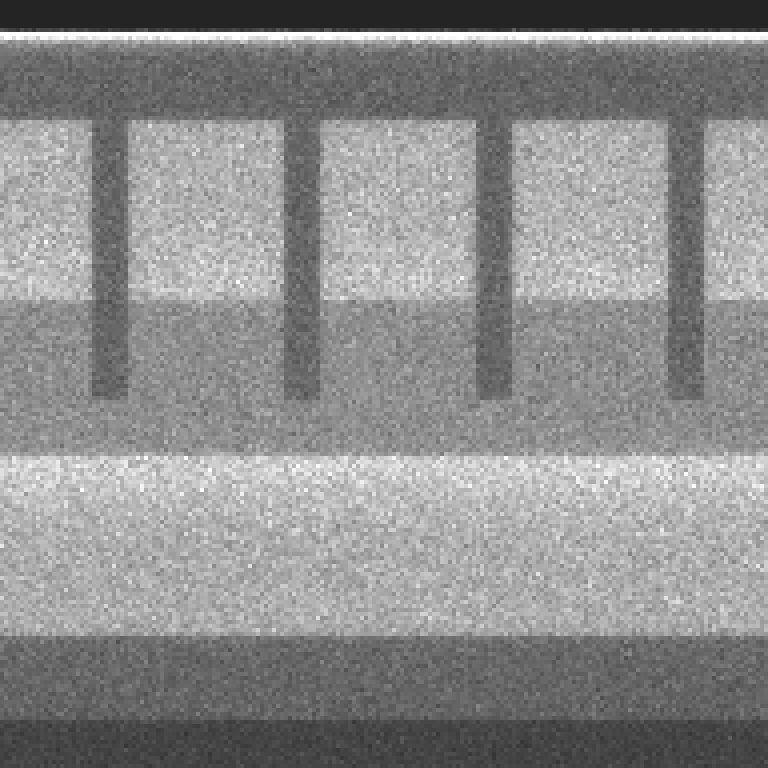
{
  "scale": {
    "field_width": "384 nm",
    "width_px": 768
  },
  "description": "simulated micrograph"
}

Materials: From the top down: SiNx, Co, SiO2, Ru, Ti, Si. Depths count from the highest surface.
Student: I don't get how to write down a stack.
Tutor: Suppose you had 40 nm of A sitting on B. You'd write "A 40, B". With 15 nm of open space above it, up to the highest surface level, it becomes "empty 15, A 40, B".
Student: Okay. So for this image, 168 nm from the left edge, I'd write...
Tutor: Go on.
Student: SiNx 44, Co 90, SiO2 78, Ru 90, Ti 42, Si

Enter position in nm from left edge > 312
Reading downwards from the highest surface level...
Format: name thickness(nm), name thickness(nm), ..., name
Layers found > SiNx 44, Co 90, SiO2 78, Ru 90, Ti 42, Si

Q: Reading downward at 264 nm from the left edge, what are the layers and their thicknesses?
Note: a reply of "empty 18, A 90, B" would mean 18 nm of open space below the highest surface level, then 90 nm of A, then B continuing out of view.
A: SiNx 44, Co 90, SiO2 78, Ru 90, Ti 42, Si